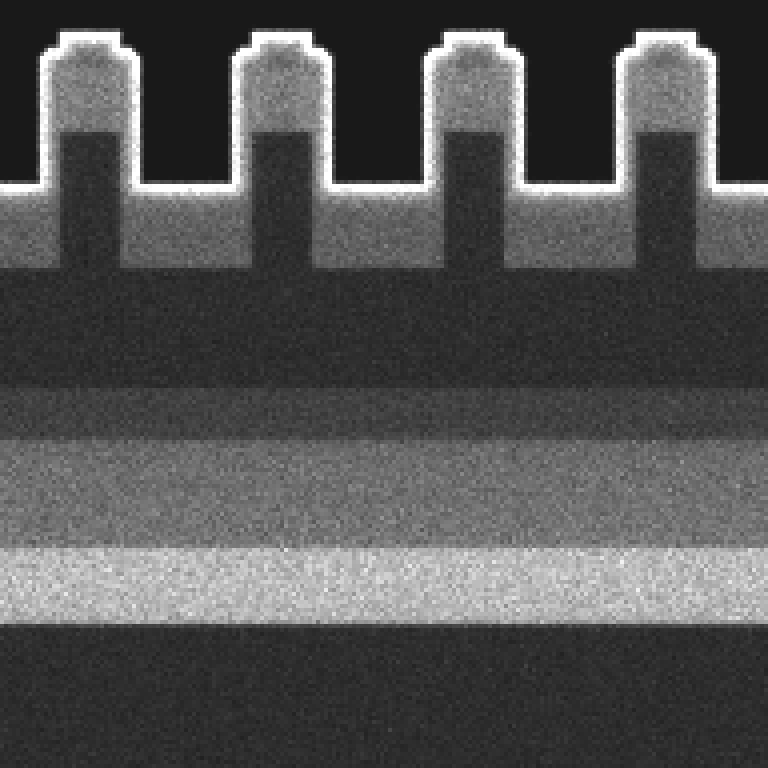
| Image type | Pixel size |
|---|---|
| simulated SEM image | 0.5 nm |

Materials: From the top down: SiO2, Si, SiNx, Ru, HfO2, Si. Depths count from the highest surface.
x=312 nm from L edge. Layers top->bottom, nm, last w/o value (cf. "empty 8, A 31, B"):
empty 8, SiO2 110, Si 60, SiNx 26, Ru 54, HfO2 38, Si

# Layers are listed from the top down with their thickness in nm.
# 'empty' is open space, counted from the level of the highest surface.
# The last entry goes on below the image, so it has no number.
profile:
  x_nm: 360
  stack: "empty 76, SiO2 42, Si 60, SiNx 26, Ru 54, HfO2 38, Si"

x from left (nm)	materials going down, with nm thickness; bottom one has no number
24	empty 8, SiO2 110, Si 60, SiNx 26, Ru 54, HfO2 38, Si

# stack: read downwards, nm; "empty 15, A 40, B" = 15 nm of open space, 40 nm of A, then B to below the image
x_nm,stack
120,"empty 8, SiO2 110, Si 60, SiNx 26, Ru 54, HfO2 38, Si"